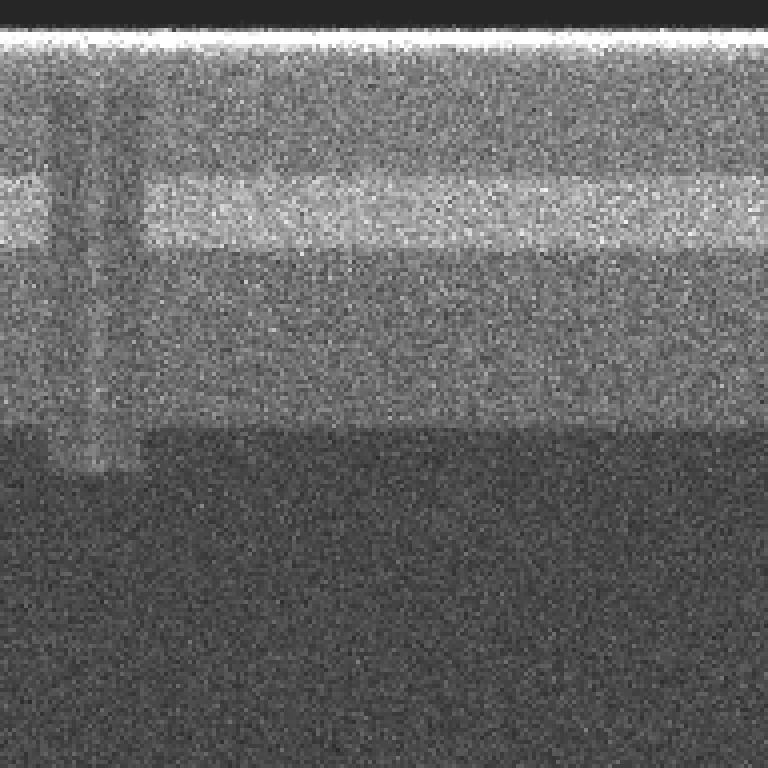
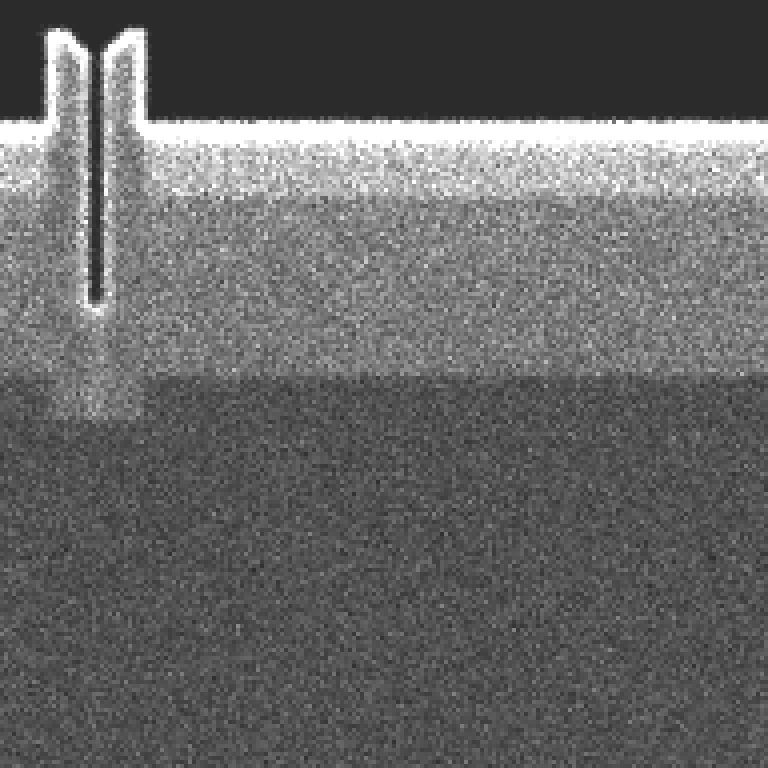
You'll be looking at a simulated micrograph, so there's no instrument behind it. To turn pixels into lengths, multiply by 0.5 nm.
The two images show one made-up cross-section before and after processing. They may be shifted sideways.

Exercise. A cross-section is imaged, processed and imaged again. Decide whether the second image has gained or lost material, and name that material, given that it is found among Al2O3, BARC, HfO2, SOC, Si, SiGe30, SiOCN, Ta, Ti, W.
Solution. removed: SOC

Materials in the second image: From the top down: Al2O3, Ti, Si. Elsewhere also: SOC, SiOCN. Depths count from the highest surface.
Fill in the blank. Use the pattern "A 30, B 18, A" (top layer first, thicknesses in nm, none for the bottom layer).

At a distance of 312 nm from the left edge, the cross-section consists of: empty 46, Al2O3 36, Ti 90, Si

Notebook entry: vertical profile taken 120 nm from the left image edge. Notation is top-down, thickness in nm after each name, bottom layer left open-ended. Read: empty 46, Al2O3 36, Ti 90, Si